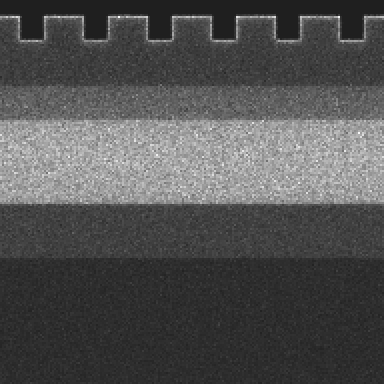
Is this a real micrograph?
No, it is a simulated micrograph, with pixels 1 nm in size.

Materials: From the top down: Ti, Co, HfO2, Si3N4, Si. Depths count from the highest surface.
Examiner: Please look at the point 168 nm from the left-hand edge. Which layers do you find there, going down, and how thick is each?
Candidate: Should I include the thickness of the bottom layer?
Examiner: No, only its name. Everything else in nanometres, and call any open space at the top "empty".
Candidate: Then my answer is empty 24, Ti 46, Co 34, HfO2 84, Si3N4 54, Si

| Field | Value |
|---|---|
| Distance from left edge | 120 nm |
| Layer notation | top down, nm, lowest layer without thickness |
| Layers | Ti 70, Co 34, HfO2 84, Si3N4 54, Si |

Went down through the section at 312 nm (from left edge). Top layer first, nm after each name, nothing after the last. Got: Ti 70, Co 34, HfO2 84, Si3N4 54, Si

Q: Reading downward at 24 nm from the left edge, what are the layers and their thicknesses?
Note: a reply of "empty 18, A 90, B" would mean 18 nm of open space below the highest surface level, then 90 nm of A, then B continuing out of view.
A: empty 24, Ti 46, Co 34, HfO2 84, Si3N4 54, Si